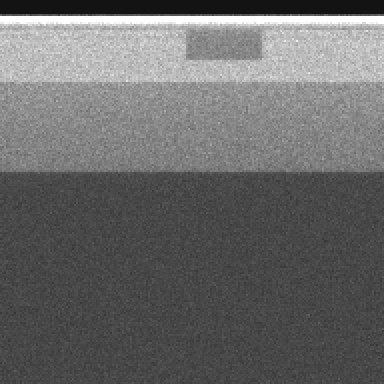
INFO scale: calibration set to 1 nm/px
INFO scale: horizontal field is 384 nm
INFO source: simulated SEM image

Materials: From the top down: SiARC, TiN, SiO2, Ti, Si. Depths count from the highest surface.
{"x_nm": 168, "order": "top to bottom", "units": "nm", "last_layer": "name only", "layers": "SiARC 14, TiN 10, SiO2 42, Ti 90, Si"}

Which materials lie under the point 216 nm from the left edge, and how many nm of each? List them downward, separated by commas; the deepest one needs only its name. SiARC 44, SiO2 22, Ti 90, Si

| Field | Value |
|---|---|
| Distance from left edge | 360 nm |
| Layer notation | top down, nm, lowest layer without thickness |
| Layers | SiARC 14, TiN 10, SiO2 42, Ti 90, Si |